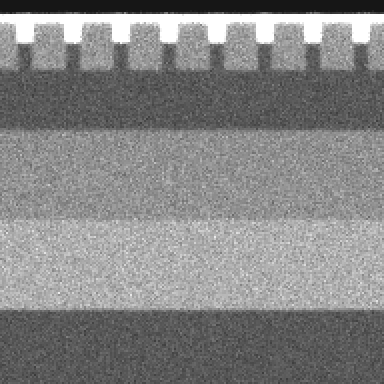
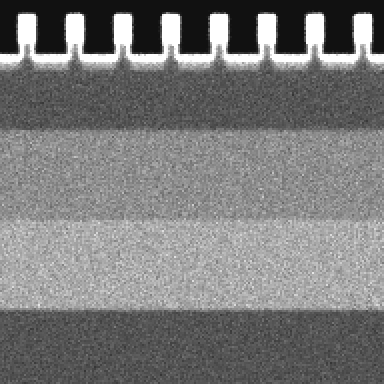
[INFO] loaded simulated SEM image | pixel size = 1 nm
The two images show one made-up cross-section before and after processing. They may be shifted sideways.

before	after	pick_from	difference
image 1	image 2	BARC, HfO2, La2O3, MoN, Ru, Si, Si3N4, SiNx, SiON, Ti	SiNx removed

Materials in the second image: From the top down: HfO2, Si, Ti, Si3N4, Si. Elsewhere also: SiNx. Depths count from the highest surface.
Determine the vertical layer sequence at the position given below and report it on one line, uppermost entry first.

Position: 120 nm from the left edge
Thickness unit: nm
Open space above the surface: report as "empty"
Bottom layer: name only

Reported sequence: HfO2 26, Si 88, Ti 90, Si3N4 90, Si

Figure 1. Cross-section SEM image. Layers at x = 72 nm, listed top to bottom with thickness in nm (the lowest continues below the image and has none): HfO2 26, Si 88, Ti 90, Si3N4 90, Si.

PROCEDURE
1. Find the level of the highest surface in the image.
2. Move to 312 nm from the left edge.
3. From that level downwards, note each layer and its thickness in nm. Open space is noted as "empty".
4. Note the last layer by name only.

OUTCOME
HfO2 26, Si 88, Ti 90, Si3N4 90, Si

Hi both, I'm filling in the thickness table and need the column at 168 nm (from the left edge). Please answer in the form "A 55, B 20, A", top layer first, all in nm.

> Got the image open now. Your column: HfO2 26, Si 88, Ti 90, Si3N4 90, Si